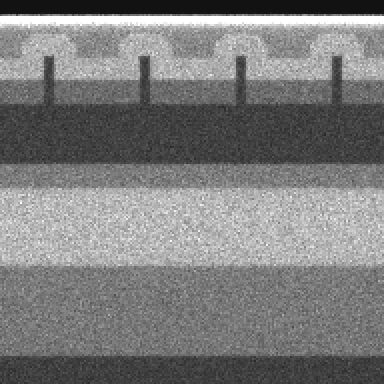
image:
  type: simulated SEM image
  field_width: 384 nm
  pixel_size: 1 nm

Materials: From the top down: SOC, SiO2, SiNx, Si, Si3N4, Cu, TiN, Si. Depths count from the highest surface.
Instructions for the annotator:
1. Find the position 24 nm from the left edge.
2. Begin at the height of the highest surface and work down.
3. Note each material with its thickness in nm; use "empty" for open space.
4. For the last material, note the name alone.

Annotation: SOC 26, SiO2 38, SiNx 24, Si 60, Si3N4 24, Cu 78, TiN 90, Si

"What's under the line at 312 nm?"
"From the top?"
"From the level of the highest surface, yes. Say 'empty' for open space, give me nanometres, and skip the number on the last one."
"SOC 26, SiO2 38, SiNx 24, Si 60, Si3N4 24, Cu 78, TiN 90, Si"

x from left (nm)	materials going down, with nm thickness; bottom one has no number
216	SOC 26, SiO2 38, SiNx 24, Si 60, Si3N4 24, Cu 78, TiN 90, Si